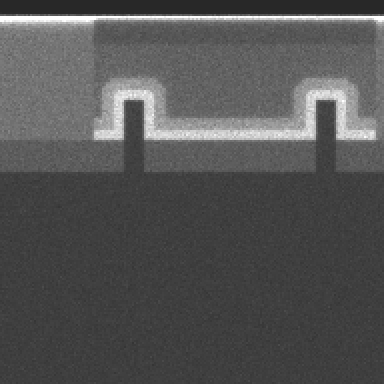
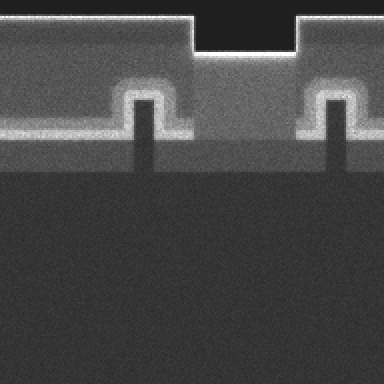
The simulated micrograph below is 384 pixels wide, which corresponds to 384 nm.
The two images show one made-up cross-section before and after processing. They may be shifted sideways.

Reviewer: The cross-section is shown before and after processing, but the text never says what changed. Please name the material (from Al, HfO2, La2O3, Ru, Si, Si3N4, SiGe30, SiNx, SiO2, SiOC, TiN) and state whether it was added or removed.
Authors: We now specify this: SiO2, removed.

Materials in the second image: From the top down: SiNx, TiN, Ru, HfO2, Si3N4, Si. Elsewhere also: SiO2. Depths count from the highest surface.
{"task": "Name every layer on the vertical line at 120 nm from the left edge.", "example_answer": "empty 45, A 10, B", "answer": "SiNx 28, TiN 36, Ru 50, HfO2 10, Si3N4 32, Si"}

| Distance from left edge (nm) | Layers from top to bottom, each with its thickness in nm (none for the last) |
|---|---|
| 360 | SiNx 28, TiN 38, Ru 48, HfO2 10, Si3N4 32, Si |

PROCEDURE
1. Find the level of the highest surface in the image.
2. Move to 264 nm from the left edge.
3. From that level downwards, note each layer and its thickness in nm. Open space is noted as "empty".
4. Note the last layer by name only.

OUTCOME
empty 36, SiO2 88, Si3N4 32, Si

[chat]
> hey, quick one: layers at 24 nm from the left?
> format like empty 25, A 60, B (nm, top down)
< SiNx 28, TiN 74, Ru 12, HfO2 10, Si3N4 32, Si